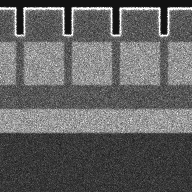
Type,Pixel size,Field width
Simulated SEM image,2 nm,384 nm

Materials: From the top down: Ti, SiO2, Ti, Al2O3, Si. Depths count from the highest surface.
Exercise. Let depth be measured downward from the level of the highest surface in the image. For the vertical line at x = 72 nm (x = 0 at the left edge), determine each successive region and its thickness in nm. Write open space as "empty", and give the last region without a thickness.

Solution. Ti 68, SiO2 86, Ti 48, Al2O3 48, Si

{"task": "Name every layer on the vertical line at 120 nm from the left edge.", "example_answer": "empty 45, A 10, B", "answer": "Ti 68, SiO2 86, Ti 48, Al2O3 48, Si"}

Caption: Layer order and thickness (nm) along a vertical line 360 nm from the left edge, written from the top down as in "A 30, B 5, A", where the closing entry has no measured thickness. Ti 68, SiO2 86, Ti 48, Al2O3 48, Si